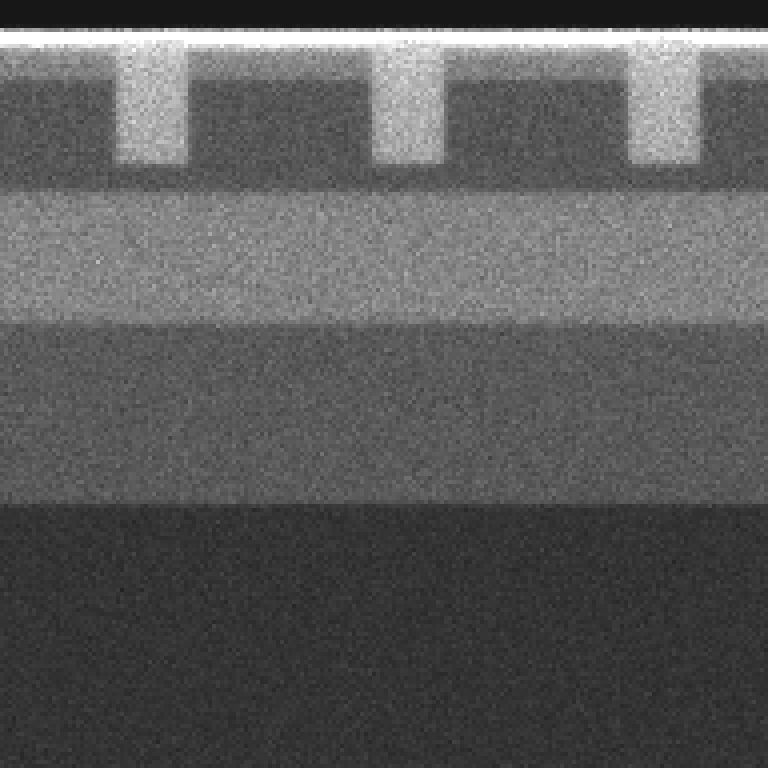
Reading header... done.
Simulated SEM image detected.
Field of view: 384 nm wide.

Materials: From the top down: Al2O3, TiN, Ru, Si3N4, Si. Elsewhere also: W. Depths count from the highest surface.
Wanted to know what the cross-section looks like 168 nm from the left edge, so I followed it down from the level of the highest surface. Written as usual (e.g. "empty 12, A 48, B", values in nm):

Al2O3 24, TiN 56, Ru 66, Si3N4 90, Si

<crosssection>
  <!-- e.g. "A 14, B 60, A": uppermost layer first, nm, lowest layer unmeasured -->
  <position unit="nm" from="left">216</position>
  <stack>W 66, TiN 14, Ru 66, Si3N4 90, Si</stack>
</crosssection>